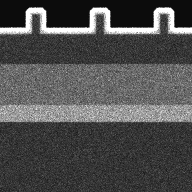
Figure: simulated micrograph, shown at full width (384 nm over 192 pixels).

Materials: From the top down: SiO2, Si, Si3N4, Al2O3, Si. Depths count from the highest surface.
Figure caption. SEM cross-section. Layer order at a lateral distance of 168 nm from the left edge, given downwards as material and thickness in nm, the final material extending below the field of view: empty 40, SiO2 12, Si 60, Si3N4 82, Al2O3 34, Si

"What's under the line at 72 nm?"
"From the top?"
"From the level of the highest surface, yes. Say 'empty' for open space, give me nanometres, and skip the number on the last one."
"SiO2 12, Si 100, Si3N4 82, Al2O3 34, Si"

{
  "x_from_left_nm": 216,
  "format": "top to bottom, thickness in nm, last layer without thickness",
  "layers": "empty 4, SiO2 48, Si 60, Si3N4 82, Al2O3 34, Si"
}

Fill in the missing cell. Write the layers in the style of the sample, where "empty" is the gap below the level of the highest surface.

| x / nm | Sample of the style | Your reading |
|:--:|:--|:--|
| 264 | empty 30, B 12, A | empty 40, SiO2 12, Si 60, Si3N4 82, Al2O3 34, Si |